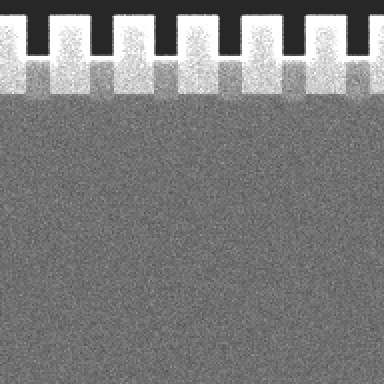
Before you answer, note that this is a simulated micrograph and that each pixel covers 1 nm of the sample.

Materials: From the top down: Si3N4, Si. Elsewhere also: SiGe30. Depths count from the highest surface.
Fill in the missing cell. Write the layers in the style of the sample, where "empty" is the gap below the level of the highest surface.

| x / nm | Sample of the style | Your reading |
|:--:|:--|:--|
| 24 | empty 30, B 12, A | Si3N4 78, Si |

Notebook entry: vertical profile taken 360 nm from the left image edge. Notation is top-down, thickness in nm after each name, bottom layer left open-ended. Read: empty 40, SiGe30 44, Si